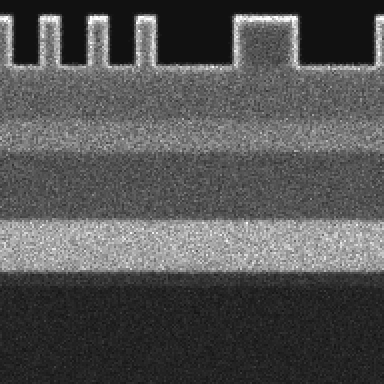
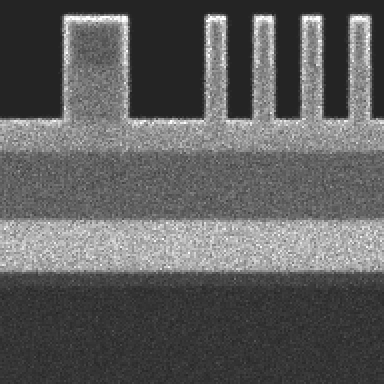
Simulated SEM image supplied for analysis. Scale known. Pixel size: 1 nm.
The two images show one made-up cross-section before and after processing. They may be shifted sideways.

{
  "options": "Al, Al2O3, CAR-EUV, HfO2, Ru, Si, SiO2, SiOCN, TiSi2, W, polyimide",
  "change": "removed",
  "material": "Ru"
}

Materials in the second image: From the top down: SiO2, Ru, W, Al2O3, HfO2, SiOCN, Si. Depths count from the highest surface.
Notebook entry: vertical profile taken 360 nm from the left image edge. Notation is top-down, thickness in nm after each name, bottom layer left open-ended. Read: SiO2 50, Ru 54, W 32, Al2O3 68, HfO2 52, SiOCN 14, Si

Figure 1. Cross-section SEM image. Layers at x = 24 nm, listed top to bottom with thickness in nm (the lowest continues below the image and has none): empty 104, W 32, Al2O3 68, HfO2 52, SiOCN 14, Si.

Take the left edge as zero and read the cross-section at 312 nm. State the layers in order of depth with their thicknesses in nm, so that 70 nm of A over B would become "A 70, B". SiO2 50, Ru 54, W 32, Al2O3 68, HfO2 52, SiOCN 14, Si